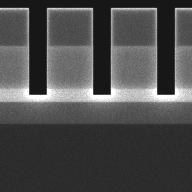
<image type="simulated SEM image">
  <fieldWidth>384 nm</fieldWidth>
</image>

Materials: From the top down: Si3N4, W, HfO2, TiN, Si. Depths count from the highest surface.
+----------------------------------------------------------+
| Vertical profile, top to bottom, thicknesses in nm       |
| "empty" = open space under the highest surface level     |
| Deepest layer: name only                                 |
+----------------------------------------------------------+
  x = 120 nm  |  Si3N4 76, W 86, HfO2 26, TiN 44, Si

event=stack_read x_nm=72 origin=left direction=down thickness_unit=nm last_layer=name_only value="empty 174, HfO2 14, TiN 44, Si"